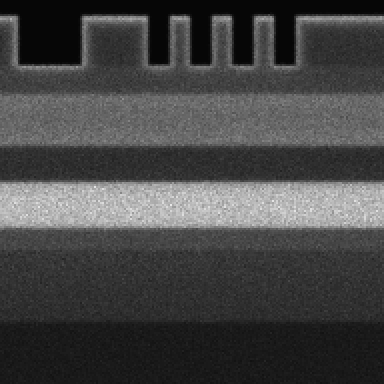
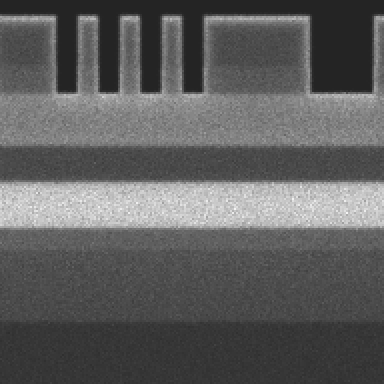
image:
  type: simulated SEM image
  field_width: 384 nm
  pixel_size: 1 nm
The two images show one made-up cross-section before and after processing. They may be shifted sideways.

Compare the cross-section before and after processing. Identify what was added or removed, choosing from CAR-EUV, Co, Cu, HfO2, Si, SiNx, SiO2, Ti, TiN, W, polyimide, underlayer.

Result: TiN removed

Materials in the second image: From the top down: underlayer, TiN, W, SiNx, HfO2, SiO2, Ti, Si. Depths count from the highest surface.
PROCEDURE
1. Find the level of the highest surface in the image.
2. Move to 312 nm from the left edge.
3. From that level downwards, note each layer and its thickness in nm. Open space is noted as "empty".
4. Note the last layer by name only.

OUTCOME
empty 78, W 52, SiNx 36, HfO2 46, SiO2 22, Ti 72, Si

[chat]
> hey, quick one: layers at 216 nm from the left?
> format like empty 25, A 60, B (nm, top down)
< underlayer 50, TiN 28, W 52, SiNx 36, HfO2 46, SiO2 22, Ti 72, Si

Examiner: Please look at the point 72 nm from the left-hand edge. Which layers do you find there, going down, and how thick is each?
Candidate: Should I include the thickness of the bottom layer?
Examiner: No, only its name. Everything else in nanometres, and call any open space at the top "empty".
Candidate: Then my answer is empty 78, W 52, SiNx 36, HfO2 46, SiO2 22, Ti 72, Si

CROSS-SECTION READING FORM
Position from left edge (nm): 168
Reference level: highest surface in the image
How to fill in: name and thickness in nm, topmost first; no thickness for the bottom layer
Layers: underlayer 50, TiN 28, W 52, SiNx 36, HfO2 46, SiO2 22, Ti 72, Si